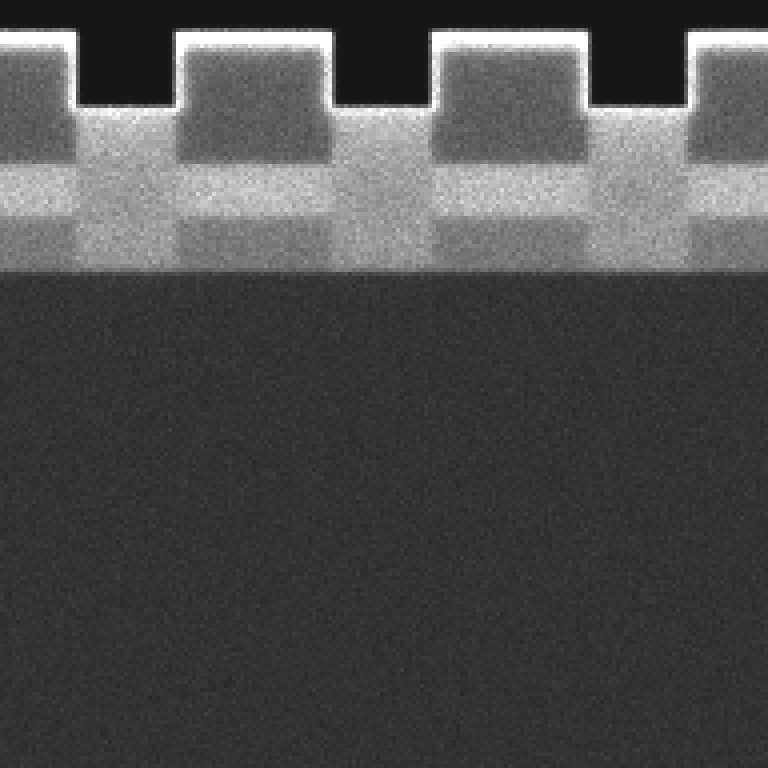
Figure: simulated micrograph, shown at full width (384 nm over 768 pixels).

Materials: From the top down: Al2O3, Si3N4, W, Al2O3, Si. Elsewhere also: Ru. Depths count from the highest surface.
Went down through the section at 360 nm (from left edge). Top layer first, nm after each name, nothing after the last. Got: Al2O3 10, Si3N4 56, W 26, Al2O3 28, Si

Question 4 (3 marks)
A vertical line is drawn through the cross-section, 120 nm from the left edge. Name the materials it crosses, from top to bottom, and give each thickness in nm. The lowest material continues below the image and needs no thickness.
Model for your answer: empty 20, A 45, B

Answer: Al2O3 10, Si3N4 56, W 26, Al2O3 28, Si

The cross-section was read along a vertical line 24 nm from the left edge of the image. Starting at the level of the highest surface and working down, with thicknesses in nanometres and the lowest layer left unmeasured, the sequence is Al2O3 10, Si3N4 56, W 26, Al2O3 28, Si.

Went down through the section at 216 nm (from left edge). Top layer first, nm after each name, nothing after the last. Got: Al2O3 10, Si3N4 56, W 26, Al2O3 28, Si